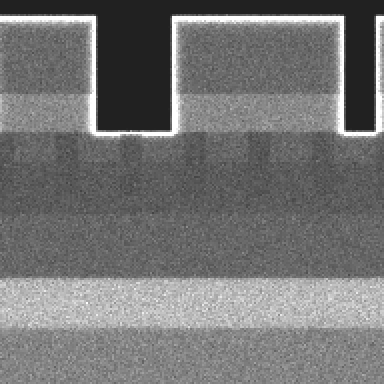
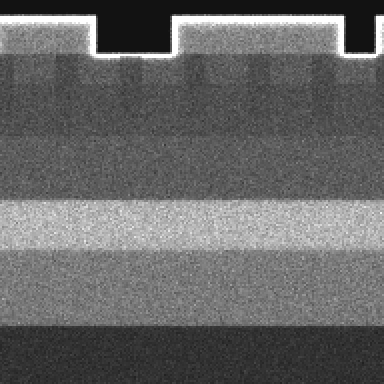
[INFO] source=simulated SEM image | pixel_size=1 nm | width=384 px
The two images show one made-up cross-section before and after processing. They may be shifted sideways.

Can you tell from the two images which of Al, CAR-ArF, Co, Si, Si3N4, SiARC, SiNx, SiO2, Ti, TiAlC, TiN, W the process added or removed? Yes, it removed SiARC.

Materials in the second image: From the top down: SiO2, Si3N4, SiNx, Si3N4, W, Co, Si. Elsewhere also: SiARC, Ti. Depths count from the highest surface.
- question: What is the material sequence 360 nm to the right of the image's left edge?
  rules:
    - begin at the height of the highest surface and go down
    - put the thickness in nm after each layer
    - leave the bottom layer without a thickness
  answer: empty 38, Si3N4 30, SiNx 52, Si3N4 64, W 50, Co 76, Si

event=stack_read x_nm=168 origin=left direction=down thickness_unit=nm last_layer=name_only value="empty 38, Si3N4 30, SiNx 52, Si3N4 64, W 50, Co 76, Si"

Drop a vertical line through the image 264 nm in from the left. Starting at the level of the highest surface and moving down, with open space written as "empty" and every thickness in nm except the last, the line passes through SiO2 38, Ti 64, SiNx 18, Si3N4 64, W 50, Co 76, Si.